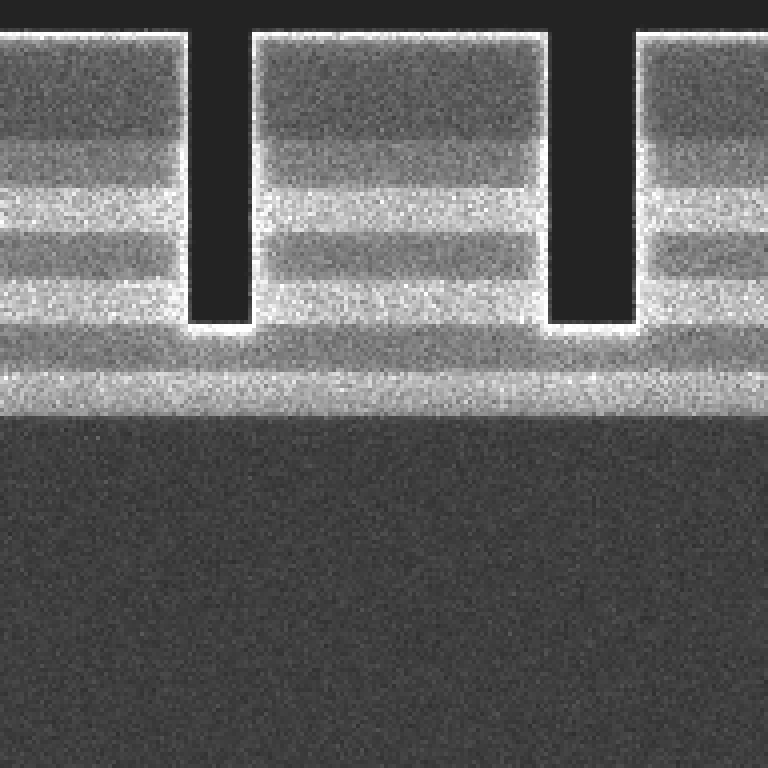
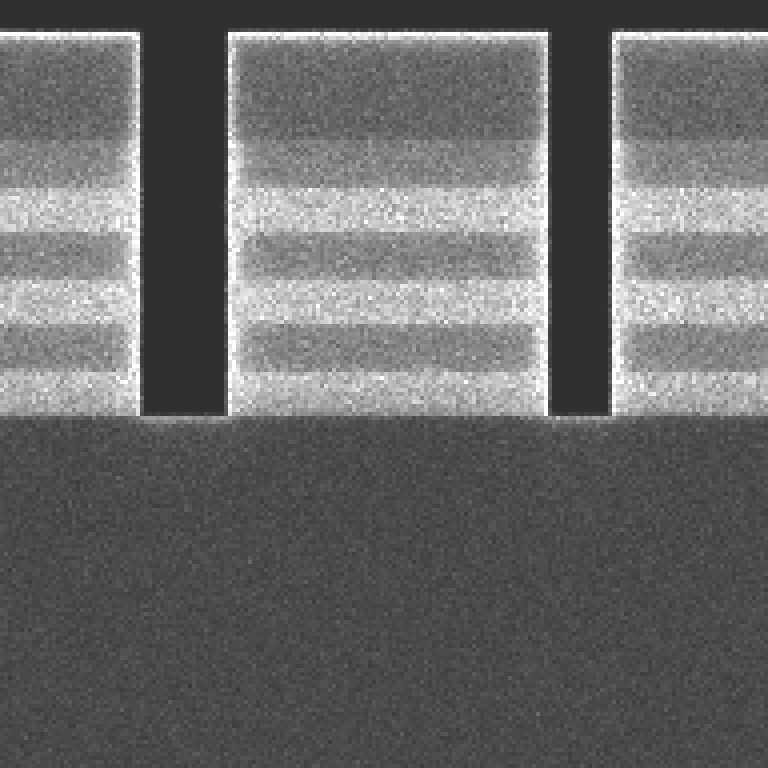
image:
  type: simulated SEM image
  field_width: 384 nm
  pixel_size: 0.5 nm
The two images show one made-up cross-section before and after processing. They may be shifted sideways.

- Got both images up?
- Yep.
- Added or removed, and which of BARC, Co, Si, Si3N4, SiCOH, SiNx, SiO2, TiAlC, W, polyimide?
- removed, SiO2 and W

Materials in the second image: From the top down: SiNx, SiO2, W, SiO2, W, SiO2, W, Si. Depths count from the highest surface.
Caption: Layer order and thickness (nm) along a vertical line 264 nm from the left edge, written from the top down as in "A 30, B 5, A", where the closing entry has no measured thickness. SiNx 54, SiO2 24, W 22, SiO2 24, W 22, SiO2 24, W 22, Si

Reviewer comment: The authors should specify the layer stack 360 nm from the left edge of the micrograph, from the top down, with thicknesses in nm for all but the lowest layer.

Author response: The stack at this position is SiNx 54, SiO2 24, W 22, SiO2 24, W 22, SiO2 24, W 22, Si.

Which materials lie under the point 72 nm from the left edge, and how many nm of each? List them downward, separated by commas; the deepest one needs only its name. empty 192, Si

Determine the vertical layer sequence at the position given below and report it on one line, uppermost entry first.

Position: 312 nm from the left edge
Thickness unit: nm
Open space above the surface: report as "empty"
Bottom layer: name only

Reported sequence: SiNx 54, SiO2 24, W 22, SiO2 24, W 22, SiO2 24, W 22, Si